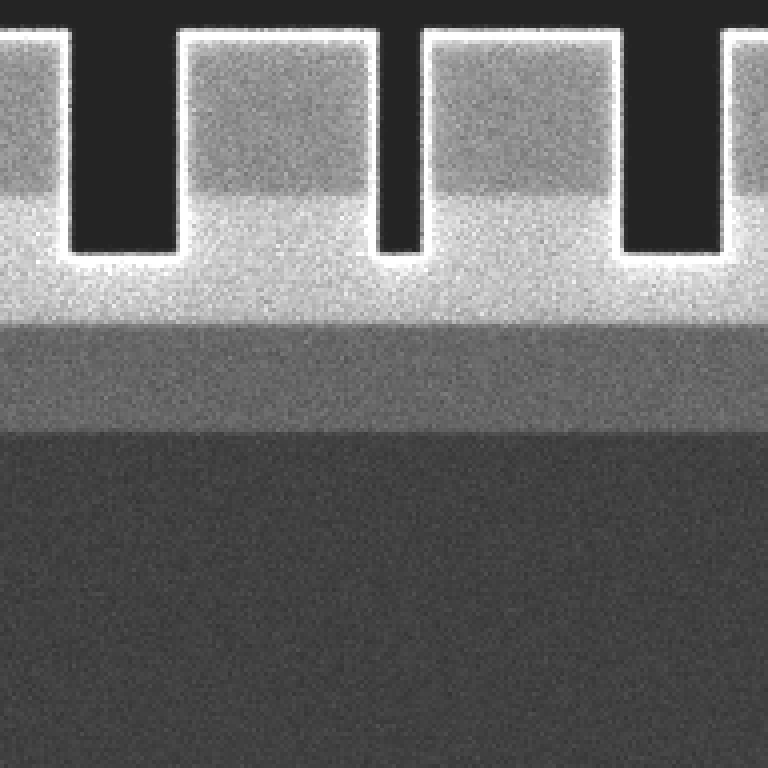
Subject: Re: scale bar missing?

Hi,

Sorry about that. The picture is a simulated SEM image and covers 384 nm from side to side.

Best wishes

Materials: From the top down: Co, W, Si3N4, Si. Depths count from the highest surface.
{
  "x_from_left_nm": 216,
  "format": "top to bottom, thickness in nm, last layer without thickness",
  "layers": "Co 82, W 64, Si3N4 54, Si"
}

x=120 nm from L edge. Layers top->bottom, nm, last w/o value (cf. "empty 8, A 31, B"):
Co 82, W 64, Si3N4 54, Si